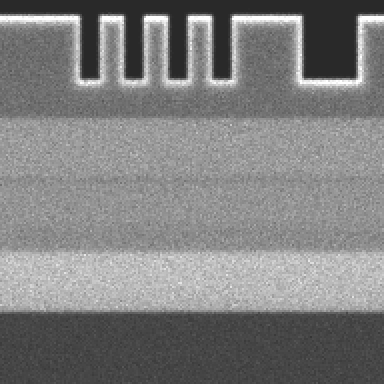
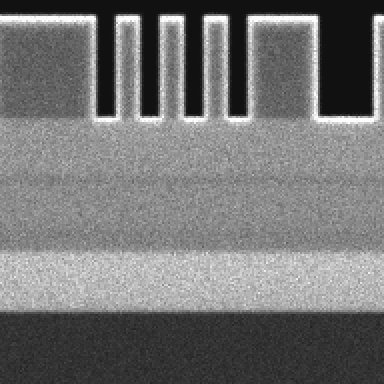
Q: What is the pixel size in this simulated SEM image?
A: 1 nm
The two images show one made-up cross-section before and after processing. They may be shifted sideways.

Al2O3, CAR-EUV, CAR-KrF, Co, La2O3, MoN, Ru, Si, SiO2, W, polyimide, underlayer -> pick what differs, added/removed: underlayer removed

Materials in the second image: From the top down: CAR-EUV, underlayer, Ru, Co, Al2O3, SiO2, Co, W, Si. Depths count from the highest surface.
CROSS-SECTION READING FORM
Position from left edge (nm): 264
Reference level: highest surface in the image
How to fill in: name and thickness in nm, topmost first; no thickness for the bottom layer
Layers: CAR-EUV 64, underlayer 38, Ru 58, Co 8, Al2O3 38, SiO2 8, Co 22, W 60, Si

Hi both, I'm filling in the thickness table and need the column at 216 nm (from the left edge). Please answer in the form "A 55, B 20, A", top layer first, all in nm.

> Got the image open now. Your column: CAR-EUV 64, underlayer 38, Ru 58, Co 8, Al2O3 38, SiO2 8, Co 22, W 60, Si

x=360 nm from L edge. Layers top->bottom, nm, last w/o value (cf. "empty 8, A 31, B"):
empty 102, Ru 58, Co 8, Al2O3 38, SiO2 8, Co 22, W 60, Si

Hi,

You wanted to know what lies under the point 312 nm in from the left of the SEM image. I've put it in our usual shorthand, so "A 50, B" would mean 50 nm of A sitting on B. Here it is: CAR-EUV 64, underlayer 38, Ru 58, Co 8, Al2O3 38, SiO2 8, Co 22, W 60, Si